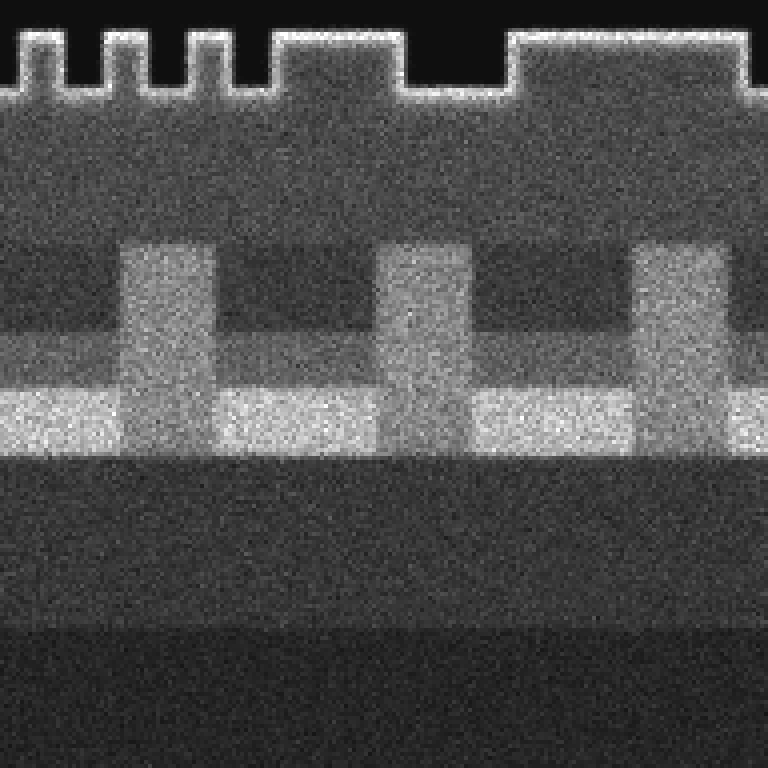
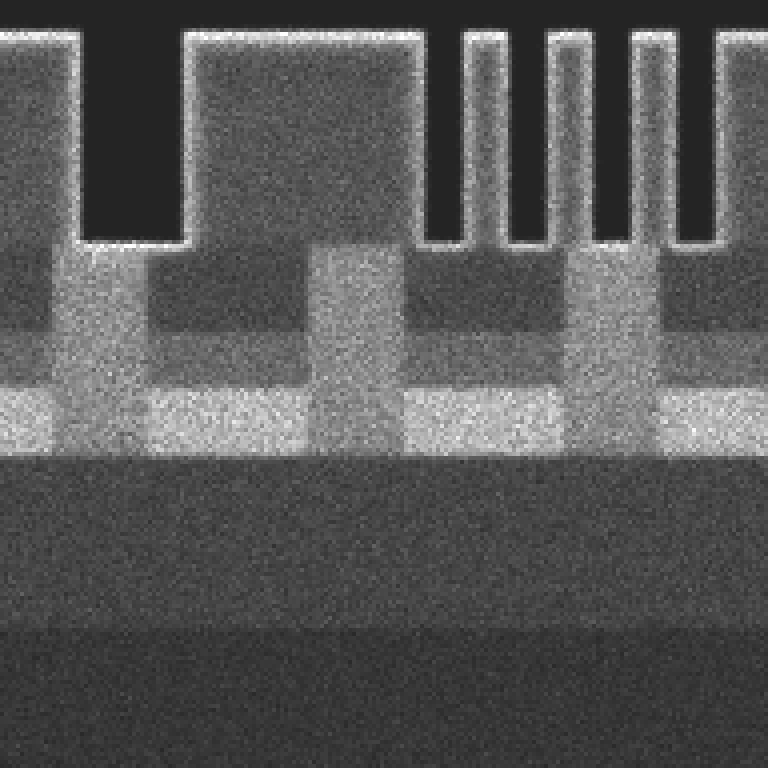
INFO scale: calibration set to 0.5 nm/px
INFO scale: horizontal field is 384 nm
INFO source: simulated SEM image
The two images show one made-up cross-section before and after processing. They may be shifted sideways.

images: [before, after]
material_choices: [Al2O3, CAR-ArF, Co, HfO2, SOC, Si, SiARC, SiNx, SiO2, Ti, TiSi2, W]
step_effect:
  removed: SOC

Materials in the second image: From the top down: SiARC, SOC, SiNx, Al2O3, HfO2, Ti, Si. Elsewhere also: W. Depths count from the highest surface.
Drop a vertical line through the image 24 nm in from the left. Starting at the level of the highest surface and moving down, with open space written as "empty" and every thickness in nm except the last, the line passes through SiARC 28, SOC 78, SiNx 44, Al2O3 28, HfO2 34, Ti 86, Si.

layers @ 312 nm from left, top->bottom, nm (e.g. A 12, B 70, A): empty 106, W 106, Ti 86, Si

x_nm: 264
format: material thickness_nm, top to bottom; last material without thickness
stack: empty 106, SiNx 44, Al2O3 28, HfO2 34, Ti 86, Si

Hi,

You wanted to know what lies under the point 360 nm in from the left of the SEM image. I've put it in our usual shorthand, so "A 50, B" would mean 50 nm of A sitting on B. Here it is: SiARC 28, SOC 78, SiNx 44, Al2O3 28, HfO2 34, Ti 86, Si